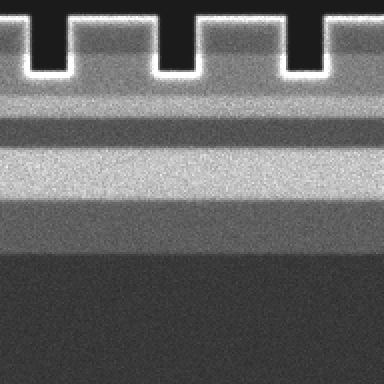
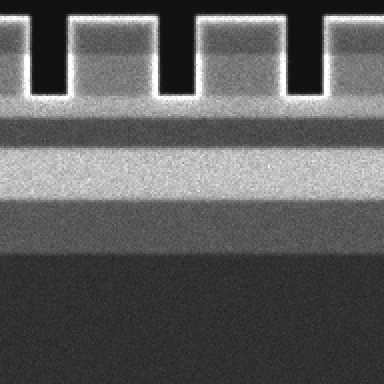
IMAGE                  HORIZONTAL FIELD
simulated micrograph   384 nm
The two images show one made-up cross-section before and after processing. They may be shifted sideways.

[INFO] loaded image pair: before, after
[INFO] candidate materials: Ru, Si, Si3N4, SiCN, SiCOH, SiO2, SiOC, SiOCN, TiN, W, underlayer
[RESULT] removed SiO2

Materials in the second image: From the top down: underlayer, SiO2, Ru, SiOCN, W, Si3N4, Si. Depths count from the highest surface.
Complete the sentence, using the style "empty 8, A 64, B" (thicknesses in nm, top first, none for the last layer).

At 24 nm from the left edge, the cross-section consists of underlayer 38, SiO2 42, Ru 22, SiOCN 30, W 52, Si3N4 54, Si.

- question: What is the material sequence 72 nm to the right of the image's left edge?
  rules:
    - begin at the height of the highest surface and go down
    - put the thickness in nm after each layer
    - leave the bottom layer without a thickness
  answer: underlayer 38, SiO2 42, Ru 22, SiOCN 30, W 52, Si3N4 54, Si